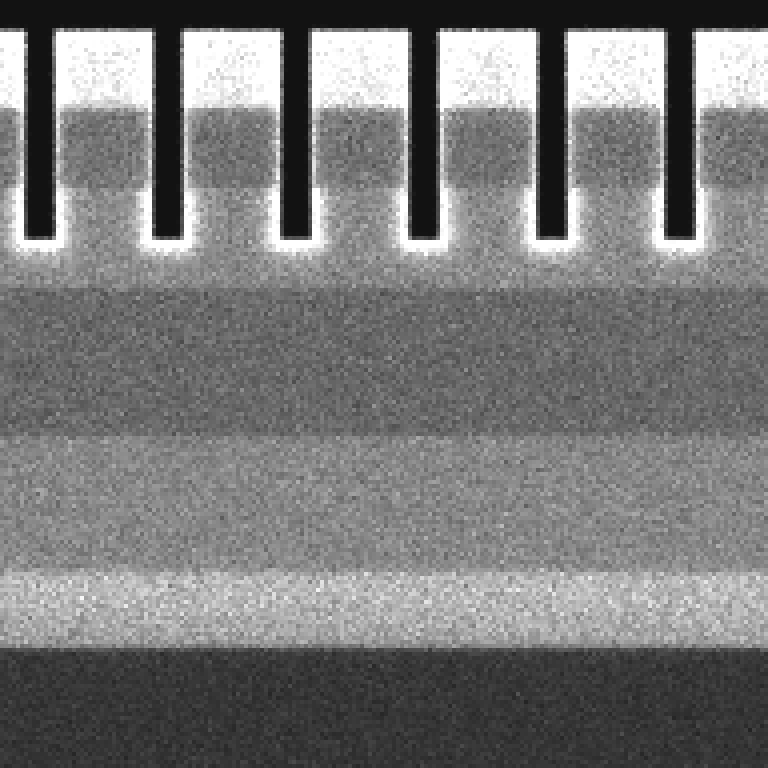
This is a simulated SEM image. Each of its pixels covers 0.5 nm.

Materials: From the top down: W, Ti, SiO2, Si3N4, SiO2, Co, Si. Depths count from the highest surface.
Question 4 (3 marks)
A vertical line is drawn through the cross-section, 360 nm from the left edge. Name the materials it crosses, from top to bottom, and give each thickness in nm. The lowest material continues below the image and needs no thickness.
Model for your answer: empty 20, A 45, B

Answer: W 38, Ti 40, SiO2 50, Si3N4 74, SiO2 68, Co 38, Si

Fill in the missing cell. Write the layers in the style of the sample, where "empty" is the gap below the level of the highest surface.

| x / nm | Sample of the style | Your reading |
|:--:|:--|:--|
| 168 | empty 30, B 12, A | W 38, Ti 40, SiO2 50, Si3N4 74, SiO2 68, Co 38, Si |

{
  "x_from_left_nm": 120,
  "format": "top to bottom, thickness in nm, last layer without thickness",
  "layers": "W 38, Ti 40, SiO2 50, Si3N4 74, SiO2 68, Co 38, Si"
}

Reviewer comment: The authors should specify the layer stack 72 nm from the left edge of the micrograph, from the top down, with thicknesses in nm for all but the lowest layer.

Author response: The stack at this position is W 38, Ti 40, SiO2 50, Si3N4 74, SiO2 68, Co 38, Si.